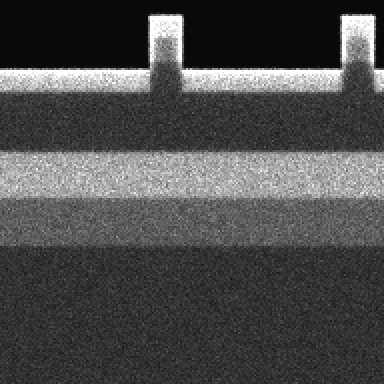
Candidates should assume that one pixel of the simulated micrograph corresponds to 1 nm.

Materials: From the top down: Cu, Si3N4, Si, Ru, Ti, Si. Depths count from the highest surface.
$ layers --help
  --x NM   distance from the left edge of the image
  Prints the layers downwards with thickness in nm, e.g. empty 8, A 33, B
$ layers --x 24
empty 54, Cu 22, Si 60, Ru 46, Ti 48, Si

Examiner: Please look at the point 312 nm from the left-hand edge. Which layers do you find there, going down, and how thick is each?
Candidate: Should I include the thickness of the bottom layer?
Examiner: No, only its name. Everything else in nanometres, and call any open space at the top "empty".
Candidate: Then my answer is empty 54, Cu 22, Si 60, Ru 46, Ti 48, Si